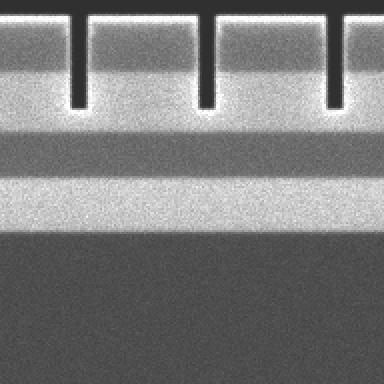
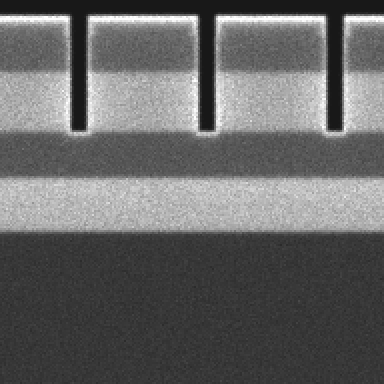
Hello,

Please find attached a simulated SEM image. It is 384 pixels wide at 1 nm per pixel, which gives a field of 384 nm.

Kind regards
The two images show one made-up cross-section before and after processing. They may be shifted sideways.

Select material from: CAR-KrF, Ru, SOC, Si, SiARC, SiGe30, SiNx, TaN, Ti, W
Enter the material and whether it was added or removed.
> Ru / removed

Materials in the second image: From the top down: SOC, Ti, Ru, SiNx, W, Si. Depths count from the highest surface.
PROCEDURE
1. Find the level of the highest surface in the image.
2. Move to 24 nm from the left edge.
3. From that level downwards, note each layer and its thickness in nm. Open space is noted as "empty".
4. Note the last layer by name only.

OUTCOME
SOC 20, Ti 36, Ru 60, SiNx 46, W 54, Si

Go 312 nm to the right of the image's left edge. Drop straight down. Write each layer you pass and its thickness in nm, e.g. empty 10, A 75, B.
SOC 20, Ti 36, Ru 60, SiNx 46, W 54, Si